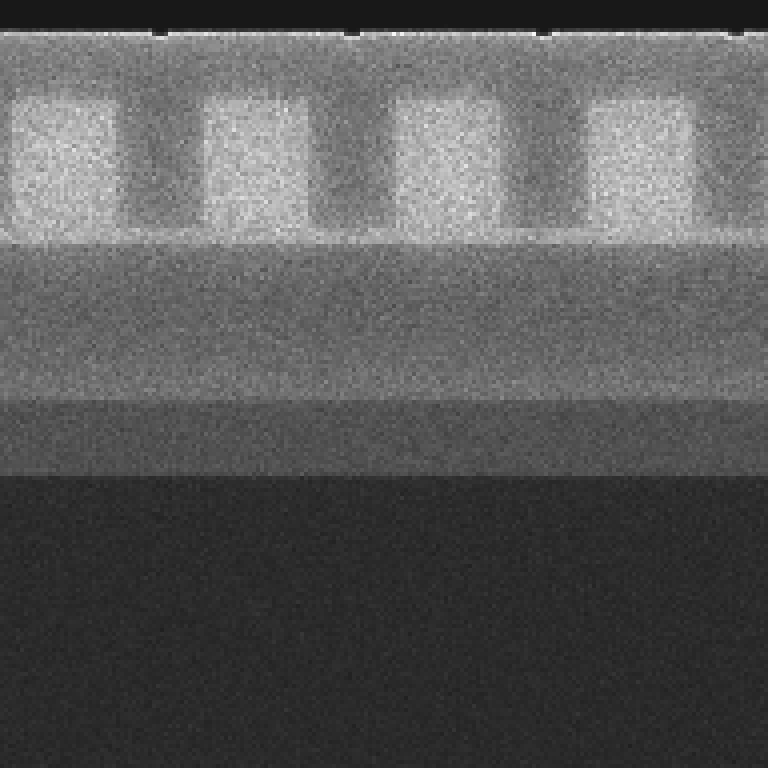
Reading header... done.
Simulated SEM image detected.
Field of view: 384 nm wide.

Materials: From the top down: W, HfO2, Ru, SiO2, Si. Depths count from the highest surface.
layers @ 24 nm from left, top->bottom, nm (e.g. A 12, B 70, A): W 34, HfO2 72, Ru 78, SiO2 38, Si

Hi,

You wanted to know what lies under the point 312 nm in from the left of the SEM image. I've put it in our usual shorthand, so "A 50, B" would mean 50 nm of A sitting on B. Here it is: W 34, HfO2 72, Ru 78, SiO2 38, Si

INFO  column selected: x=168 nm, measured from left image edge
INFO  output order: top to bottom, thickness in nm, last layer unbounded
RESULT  W 98, HfO2 8, Ru 78, SiO2 38, Si